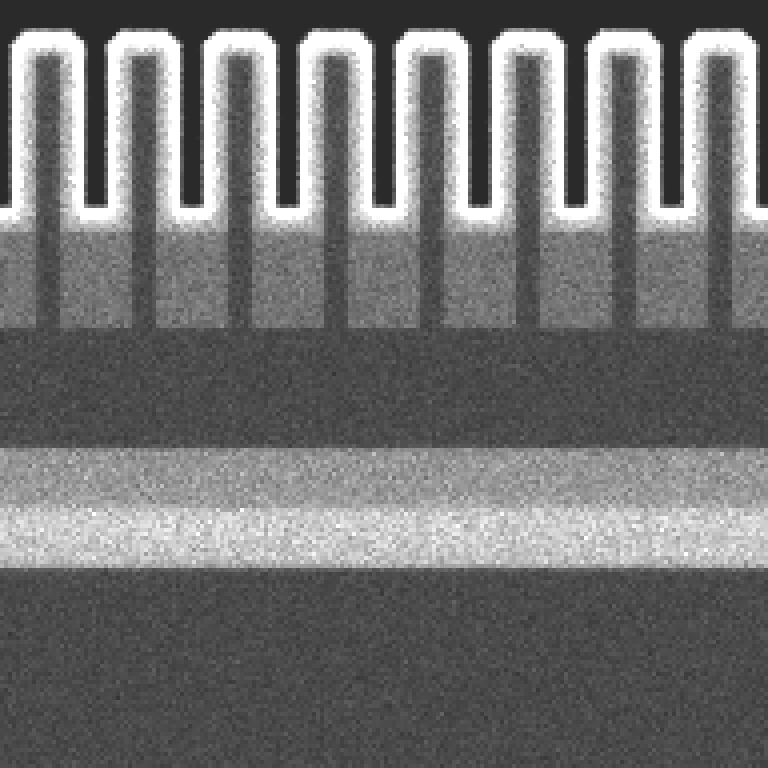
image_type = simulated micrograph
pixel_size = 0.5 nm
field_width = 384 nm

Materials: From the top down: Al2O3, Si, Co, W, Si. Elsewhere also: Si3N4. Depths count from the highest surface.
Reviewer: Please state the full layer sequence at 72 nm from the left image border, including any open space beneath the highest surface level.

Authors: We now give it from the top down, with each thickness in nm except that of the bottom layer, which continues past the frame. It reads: Al2O3 12, Si 196, Co 30, W 30, Si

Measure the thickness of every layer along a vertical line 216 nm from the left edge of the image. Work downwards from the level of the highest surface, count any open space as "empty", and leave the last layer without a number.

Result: Al2O3 12, Si 196, Co 30, W 30, Si